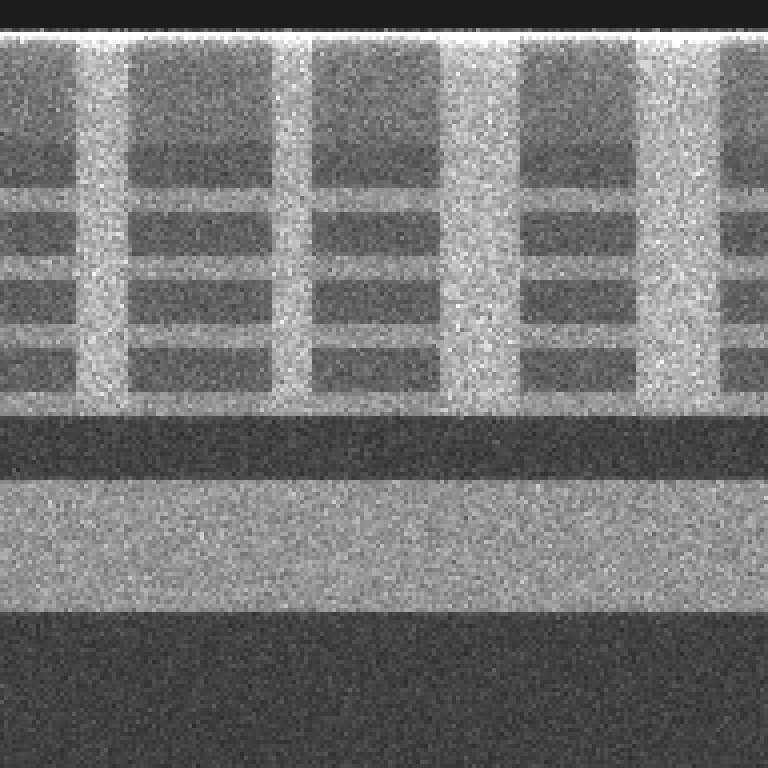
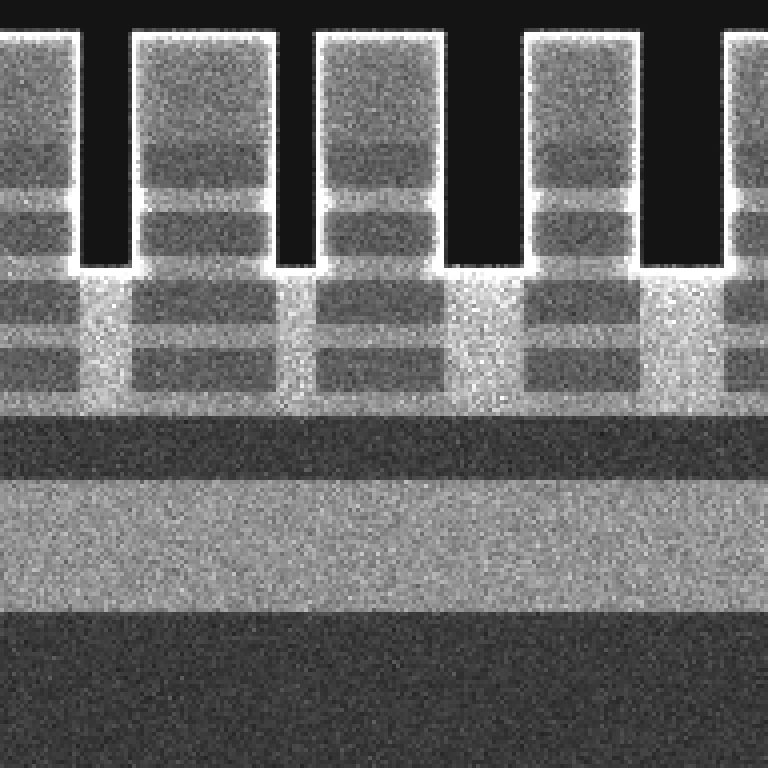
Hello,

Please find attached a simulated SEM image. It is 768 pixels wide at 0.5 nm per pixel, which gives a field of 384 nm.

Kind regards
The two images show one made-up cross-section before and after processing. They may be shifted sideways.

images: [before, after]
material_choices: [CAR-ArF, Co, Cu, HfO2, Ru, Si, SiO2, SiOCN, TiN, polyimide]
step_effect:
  removed: Co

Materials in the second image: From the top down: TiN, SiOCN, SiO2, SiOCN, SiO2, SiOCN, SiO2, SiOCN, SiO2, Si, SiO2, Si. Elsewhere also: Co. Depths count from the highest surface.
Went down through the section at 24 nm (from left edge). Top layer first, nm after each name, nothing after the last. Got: TiN 56, SiOCN 22, SiO2 12, SiOCN 22, SiO2 12, SiOCN 22, SiO2 12, SiOCN 22, SiO2 12, Si 32, SiO2 66, Si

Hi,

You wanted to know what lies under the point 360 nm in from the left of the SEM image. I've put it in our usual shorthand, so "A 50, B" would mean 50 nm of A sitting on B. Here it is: empty 118, Co 74, Si 32, SiO2 66, Si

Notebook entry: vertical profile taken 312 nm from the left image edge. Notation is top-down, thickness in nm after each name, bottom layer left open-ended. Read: TiN 56, SiOCN 22, SiO2 12, SiOCN 22, SiO2 12, SiOCN 22, SiO2 12, SiOCN 22, SiO2 12, Si 32, SiO2 66, Si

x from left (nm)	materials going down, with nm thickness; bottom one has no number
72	TiN 56, SiOCN 22, SiO2 12, SiOCN 22, SiO2 12, SiOCN 22, SiO2 12, SiOCN 22, SiO2 12, Si 32, SiO2 66, Si